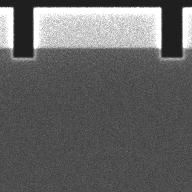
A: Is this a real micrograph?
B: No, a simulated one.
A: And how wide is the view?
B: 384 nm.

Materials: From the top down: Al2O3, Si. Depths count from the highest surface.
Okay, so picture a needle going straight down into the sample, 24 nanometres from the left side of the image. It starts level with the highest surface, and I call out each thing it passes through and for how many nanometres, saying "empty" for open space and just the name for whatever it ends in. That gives Al2O3 80, Si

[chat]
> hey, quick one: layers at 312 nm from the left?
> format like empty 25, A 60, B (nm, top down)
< Al2O3 80, Si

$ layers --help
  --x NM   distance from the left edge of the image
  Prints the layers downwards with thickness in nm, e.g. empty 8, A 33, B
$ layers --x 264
Al2O3 80, Si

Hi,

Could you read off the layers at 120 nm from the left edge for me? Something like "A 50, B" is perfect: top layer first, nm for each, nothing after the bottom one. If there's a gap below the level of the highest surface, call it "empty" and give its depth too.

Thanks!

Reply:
Al2O3 80, Si